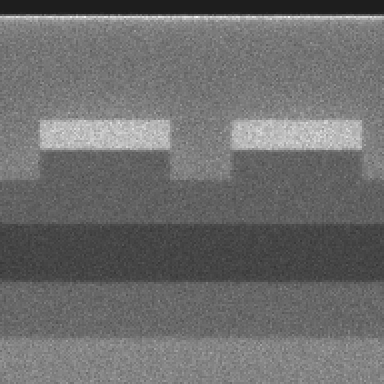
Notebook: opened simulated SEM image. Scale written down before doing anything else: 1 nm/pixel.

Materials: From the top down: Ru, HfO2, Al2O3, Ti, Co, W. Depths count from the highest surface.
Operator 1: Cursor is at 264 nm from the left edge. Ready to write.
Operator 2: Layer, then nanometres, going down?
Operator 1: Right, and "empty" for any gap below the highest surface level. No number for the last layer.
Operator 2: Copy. Ru 104, HfO2 30, Al2O3 74, Ti 58, Co 56, W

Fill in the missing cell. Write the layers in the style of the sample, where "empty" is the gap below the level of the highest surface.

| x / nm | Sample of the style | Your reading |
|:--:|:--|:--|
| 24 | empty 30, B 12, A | Ru 164, Al2O3 44, Ti 58, Co 56, W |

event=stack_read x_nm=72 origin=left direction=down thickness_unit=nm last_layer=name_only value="Ru 104, HfO2 30, Al2O3 74, Ti 58, Co 56, W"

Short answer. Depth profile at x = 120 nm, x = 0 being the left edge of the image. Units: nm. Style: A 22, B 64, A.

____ Ru 104, HfO2 30, Al2O3 74, Ti 58, Co 56, W